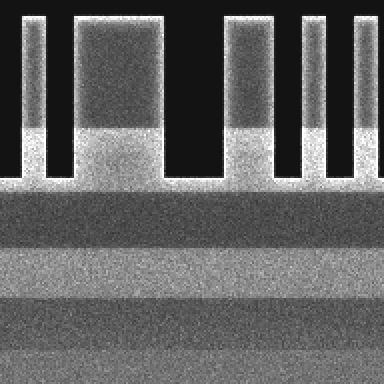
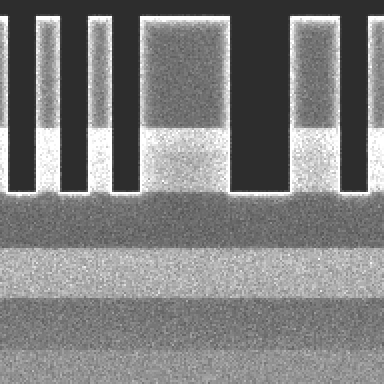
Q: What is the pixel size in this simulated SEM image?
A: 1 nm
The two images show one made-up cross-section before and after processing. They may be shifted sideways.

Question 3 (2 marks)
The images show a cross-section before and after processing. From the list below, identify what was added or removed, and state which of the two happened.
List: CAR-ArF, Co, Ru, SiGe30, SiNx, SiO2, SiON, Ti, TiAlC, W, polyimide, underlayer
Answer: Ru was removed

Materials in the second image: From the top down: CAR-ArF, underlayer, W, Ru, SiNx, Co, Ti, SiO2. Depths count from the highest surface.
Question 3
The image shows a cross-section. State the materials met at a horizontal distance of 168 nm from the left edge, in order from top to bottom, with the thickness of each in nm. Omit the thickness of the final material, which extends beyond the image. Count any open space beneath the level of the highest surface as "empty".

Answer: CAR-ArF 72, underlayer 40, W 24, Ru 40, SiNx 56, Co 50, Ti 52, SiO2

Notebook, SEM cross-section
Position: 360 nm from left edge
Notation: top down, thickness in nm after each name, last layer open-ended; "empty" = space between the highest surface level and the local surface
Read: empty 176, SiNx 56, Co 50, Ti 52, SiO2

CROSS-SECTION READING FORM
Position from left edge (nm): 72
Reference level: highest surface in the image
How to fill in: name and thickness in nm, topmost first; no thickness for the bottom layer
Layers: empty 176, SiNx 56, Co 50, Ti 52, SiO2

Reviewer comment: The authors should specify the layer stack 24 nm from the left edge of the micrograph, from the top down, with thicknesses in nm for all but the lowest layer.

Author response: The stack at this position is empty 176, SiNx 56, Co 50, Ti 52, SiO2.